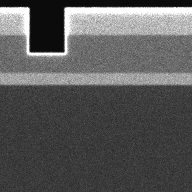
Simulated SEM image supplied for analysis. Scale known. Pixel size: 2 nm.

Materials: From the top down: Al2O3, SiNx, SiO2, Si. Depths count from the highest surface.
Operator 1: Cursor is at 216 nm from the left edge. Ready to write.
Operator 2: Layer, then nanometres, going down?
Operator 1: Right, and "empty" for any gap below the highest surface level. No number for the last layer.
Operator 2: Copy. Al2O3 54, SiNx 76, SiO2 24, Si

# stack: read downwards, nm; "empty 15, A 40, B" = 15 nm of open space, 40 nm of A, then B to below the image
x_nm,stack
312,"Al2O3 54, SiNx 76, SiO2 24, Si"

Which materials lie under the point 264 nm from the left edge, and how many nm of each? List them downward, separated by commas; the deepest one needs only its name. Al2O3 54, SiNx 76, SiO2 24, Si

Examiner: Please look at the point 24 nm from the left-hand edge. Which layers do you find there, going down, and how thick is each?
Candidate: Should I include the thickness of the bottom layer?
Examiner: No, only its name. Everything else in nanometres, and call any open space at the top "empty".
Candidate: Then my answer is Al2O3 54, SiNx 76, SiO2 24, Si